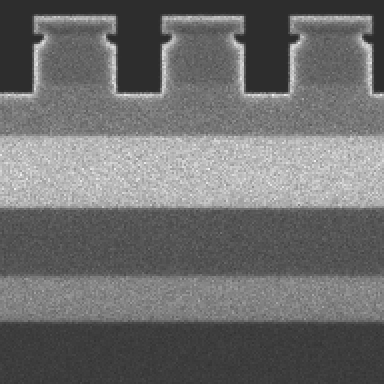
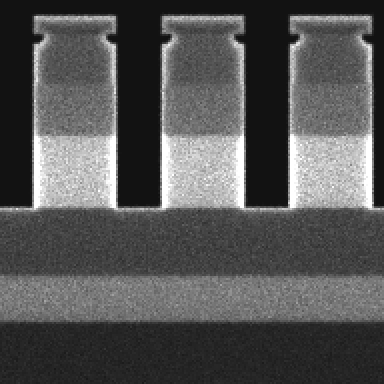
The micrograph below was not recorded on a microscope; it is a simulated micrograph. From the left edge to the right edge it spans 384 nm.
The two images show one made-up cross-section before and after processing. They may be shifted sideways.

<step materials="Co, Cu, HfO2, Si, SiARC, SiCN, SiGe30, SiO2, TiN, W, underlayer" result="removed Co and HfO2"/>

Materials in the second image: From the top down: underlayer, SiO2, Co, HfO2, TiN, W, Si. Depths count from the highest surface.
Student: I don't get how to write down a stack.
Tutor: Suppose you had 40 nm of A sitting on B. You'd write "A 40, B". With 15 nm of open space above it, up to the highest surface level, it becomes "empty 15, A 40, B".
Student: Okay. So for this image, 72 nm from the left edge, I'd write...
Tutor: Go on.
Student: underlayer 18, SiO2 50, Co 52, HfO2 72, TiN 68, W 46, Si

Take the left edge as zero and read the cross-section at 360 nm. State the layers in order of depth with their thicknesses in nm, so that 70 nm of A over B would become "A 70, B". underlayer 18, SiO2 50, Co 52, HfO2 72, TiN 68, W 46, Si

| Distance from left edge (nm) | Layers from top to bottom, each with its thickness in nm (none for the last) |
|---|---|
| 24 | empty 192, TiN 68, W 46, Si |